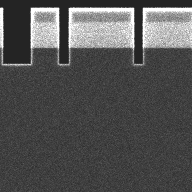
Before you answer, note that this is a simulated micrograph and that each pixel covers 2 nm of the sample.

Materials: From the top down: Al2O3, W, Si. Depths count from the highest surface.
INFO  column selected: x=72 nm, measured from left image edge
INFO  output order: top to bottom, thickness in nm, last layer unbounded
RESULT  Al2O3 28, W 52, Si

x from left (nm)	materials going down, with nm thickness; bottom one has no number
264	Al2O3 28, W 52, Si